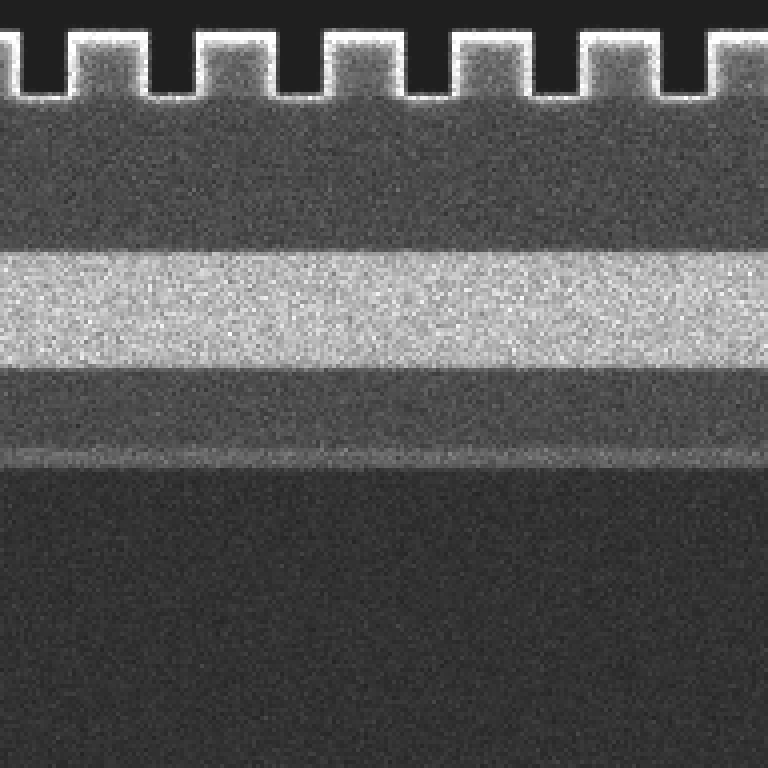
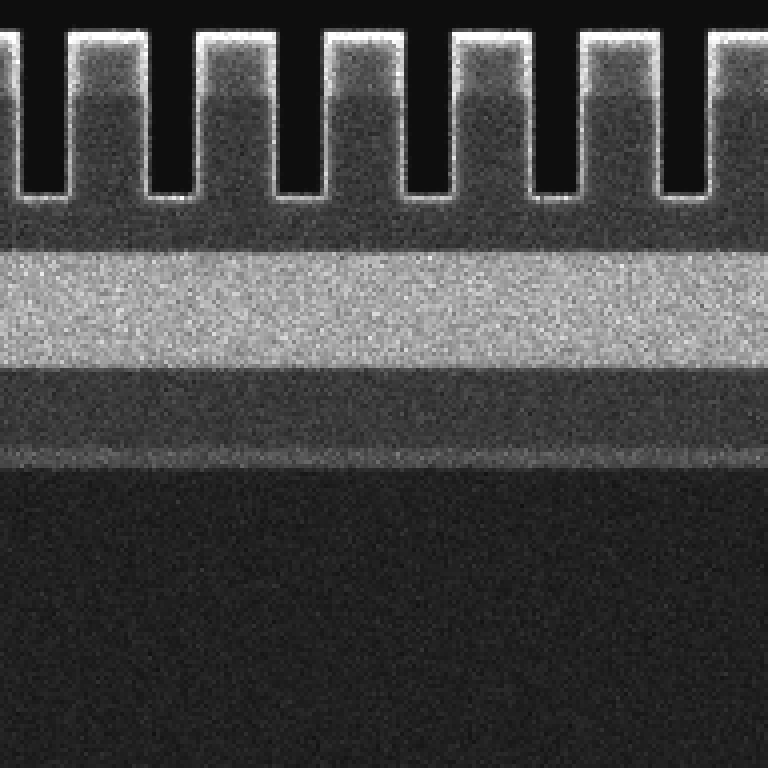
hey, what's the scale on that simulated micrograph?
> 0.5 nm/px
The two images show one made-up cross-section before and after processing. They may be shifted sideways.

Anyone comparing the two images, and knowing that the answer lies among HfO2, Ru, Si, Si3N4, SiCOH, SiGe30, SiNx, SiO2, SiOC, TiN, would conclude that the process removed TiN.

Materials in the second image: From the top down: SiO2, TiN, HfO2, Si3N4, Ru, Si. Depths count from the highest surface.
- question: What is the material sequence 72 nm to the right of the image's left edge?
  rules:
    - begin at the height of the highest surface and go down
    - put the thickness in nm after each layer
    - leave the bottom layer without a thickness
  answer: SiO2 32, TiN 78, HfO2 58, Si3N4 40, Ru 10, Si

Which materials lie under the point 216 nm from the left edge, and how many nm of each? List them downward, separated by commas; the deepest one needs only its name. empty 82, TiN 28, HfO2 58, Si3N4 40, Ru 10, Si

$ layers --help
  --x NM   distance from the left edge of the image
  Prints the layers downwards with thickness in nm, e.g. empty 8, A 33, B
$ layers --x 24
empty 82, TiN 28, HfO2 58, Si3N4 40, Ru 10, Si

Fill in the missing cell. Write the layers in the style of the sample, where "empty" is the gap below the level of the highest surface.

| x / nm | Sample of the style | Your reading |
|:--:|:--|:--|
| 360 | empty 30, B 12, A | SiO2 32, TiN 78, HfO2 58, Si3N4 40, Ru 10, Si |